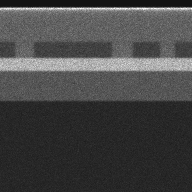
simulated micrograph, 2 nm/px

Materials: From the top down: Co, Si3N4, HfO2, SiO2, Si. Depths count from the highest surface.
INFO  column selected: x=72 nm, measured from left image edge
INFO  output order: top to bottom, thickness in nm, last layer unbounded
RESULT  Co 68, Si3N4 32, HfO2 26, SiO2 60, Si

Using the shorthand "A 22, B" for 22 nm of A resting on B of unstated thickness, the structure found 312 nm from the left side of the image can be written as Co 68, Si3N4 32, HfO2 26, SiO2 60, Si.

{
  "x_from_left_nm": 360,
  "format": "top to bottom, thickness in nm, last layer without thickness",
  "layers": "Co 68, Si3N4 32, HfO2 26, SiO2 60, Si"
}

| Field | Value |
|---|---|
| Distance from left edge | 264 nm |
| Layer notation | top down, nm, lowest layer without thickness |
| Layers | Co 100, HfO2 26, SiO2 60, Si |